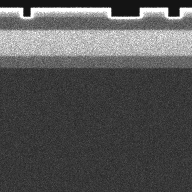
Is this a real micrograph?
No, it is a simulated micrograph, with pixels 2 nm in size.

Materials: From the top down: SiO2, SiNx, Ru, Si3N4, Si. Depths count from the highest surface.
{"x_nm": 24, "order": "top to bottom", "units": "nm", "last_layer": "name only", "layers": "SiO2 18, SiNx 26, Ru 52, Si3N4 24, Si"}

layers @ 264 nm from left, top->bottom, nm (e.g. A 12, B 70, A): empty 18, SiNx 26, Ru 52, Si3N4 24, Si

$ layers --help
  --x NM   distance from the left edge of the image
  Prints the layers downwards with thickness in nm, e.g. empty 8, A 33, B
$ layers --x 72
SiO2 18, SiNx 26, Ru 52, Si3N4 24, Si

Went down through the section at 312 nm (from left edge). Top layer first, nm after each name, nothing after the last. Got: SiO2 18, SiNx 26, Ru 52, Si3N4 24, Si